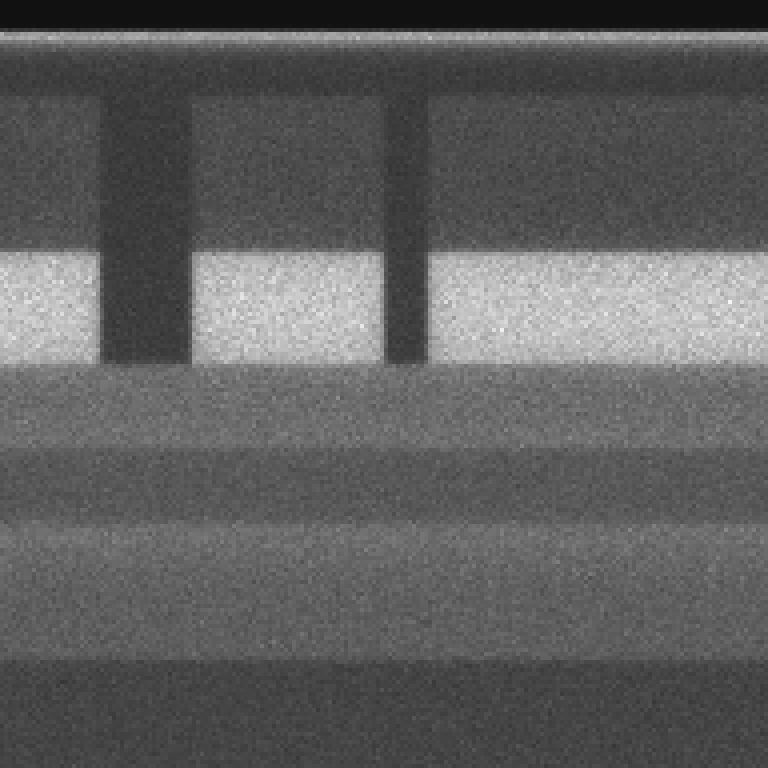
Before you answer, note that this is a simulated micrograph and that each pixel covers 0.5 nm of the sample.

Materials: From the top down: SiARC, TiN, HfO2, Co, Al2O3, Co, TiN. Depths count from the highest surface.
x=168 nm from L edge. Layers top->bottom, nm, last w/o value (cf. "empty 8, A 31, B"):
SiARC 32, TiN 78, HfO2 56, Co 42, Al2O3 38, Co 68, TiN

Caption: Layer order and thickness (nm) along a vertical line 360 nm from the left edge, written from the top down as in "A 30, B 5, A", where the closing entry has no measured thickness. SiARC 32, TiN 78, HfO2 56, Co 42, Al2O3 38, Co 68, TiN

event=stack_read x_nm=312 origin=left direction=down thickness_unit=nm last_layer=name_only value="SiARC 32, TiN 78, HfO2 56, Co 42, Al2O3 38, Co 68, TiN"